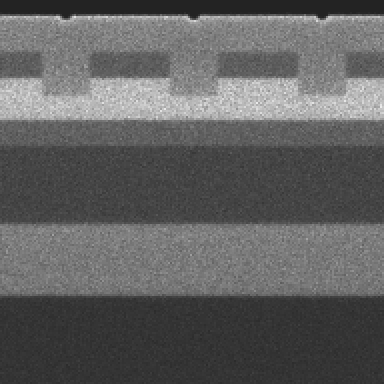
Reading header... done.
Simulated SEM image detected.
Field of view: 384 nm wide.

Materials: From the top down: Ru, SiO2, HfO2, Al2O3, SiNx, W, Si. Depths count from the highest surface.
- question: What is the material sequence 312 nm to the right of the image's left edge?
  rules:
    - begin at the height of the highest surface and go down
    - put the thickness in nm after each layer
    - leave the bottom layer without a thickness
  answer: Ru 80, HfO2 24, Al2O3 26, SiNx 78, W 72, Si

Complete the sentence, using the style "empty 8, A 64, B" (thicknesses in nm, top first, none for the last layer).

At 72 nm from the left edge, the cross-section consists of Ru 80, HfO2 24, Al2O3 26, SiNx 78, W 72, Si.